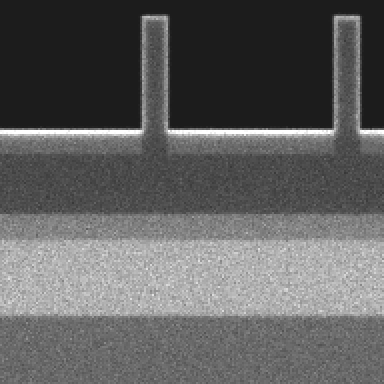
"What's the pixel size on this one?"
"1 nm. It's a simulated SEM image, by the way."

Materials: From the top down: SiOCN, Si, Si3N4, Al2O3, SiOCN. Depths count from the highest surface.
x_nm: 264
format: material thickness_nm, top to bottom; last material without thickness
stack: empty 114, SiOCN 24, Si 60, Si3N4 26, Al2O3 76, SiOCN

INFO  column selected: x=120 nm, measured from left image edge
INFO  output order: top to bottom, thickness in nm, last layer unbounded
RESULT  empty 114, SiOCN 24, Si 60, Si3N4 26, Al2O3 76, SiOCN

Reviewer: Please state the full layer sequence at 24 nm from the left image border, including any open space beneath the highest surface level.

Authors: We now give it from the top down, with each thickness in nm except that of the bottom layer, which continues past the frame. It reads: empty 114, SiOCN 24, Si 60, Si3N4 26, Al2O3 76, SiOCN